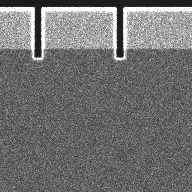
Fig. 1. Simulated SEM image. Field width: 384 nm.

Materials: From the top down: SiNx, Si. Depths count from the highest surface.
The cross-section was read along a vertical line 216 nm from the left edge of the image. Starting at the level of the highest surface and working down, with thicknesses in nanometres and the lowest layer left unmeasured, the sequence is SiNx 82, Si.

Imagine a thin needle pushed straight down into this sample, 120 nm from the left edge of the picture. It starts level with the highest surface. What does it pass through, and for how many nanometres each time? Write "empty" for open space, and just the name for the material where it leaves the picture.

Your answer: SiNx 82, Si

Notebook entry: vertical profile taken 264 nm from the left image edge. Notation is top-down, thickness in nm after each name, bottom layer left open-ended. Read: SiNx 82, Si